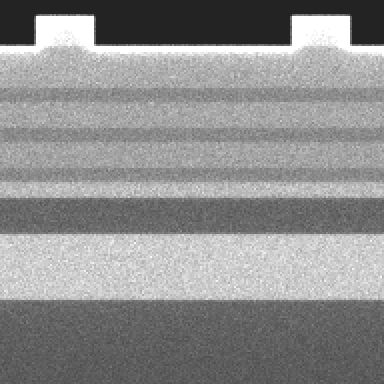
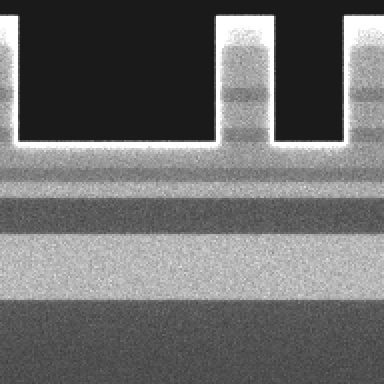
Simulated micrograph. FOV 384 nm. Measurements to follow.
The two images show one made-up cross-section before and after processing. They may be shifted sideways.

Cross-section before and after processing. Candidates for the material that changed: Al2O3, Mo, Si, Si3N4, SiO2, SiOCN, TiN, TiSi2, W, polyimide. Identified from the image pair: Si3N4 and SiOCN (removed).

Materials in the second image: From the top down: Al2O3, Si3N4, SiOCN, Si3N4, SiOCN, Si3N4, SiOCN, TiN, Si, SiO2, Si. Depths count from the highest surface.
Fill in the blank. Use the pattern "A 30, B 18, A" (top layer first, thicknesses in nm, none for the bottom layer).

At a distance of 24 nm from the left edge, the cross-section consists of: empty 126, Si3N4 26, SiOCN 14, TiN 16, Si 36, SiO2 66, Si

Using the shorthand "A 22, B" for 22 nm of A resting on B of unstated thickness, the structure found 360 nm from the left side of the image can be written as Al2O3 30, Si3N4 42, SiOCN 14, Si3N4 26, SiOCN 14, Si3N4 26, SiOCN 14, TiN 16, Si 36, SiO2 66, Si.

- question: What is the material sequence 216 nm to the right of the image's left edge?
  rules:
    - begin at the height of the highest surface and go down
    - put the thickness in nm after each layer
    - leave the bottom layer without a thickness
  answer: Al2O3 30, Si3N4 42, SiOCN 14, Si3N4 26, SiOCN 14, Si3N4 26, SiOCN 14, TiN 16, Si 36, SiO2 66, Si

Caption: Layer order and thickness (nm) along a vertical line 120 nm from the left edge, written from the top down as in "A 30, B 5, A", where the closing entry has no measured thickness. empty 126, Si3N4 26, SiOCN 14, TiN 16, Si 36, SiO2 66, Si